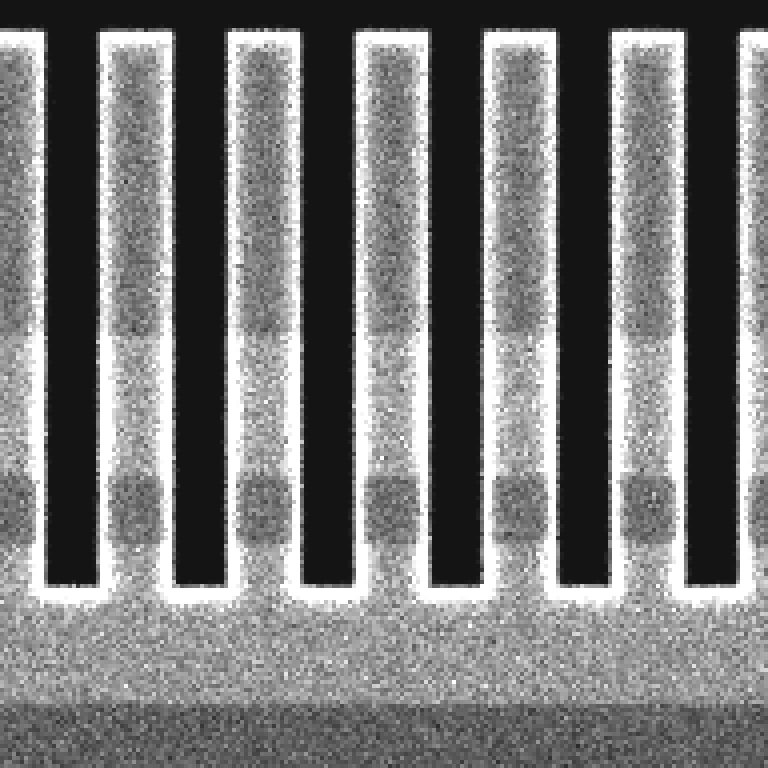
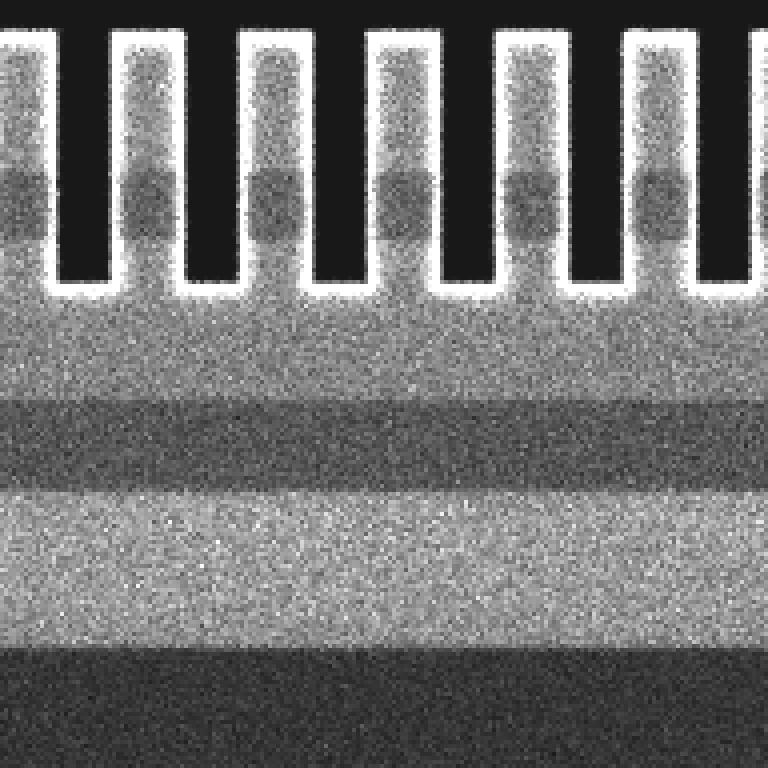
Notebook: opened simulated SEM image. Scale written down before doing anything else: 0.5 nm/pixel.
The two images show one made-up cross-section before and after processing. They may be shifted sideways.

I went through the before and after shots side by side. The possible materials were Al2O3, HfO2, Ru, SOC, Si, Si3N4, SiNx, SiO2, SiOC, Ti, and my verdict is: removed, SOC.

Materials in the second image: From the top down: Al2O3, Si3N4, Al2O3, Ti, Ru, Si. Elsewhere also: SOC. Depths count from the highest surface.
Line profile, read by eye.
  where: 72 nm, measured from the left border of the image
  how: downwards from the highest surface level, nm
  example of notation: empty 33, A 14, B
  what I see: Al2O3 70, Si3N4 34, Al2O3 80, Ti 46, Ru 78, Si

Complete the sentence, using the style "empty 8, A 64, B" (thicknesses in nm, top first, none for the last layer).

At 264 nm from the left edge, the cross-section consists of Al2O3 70, Si3N4 34, Al2O3 80, Ti 46, Ru 78, Si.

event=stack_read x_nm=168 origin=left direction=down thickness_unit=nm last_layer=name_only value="empty 126, Al2O3 58, Ti 46, Ru 78, Si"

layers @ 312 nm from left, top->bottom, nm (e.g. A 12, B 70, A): Al2O3 70, Si3N4 34, Al2O3 80, Ti 46, Ru 78, Si